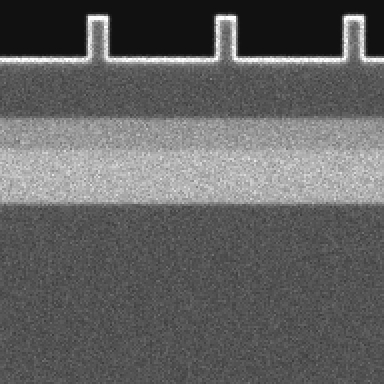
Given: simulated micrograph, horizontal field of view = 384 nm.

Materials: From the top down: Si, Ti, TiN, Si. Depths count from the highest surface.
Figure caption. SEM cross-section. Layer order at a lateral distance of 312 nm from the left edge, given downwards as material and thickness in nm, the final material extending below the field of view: empty 42, Si 60, Ti 32, TiN 54, Si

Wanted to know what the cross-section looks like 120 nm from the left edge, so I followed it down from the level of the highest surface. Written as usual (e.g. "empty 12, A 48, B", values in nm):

empty 42, Si 60, Ti 32, TiN 54, Si